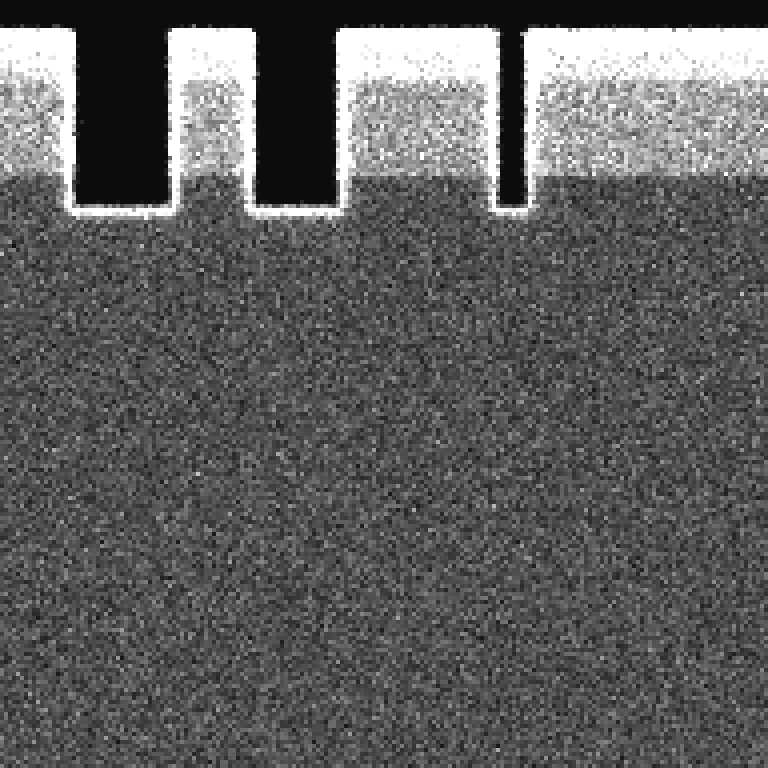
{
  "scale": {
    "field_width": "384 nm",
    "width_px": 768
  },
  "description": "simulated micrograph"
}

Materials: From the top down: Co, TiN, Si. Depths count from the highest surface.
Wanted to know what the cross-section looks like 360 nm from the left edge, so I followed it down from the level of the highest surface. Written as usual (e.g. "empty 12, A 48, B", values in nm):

Co 24, TiN 48, Si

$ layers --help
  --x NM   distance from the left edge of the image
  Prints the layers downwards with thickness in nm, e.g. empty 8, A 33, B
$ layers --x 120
Co 24, TiN 48, Si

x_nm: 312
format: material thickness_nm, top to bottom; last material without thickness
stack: Co 24, TiN 48, Si